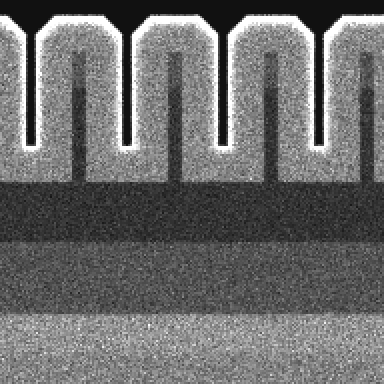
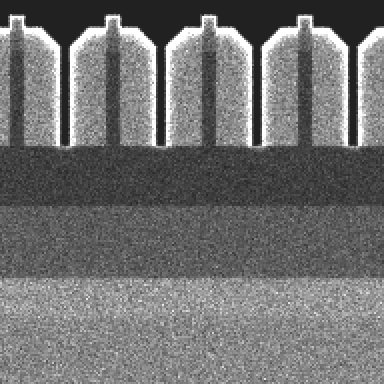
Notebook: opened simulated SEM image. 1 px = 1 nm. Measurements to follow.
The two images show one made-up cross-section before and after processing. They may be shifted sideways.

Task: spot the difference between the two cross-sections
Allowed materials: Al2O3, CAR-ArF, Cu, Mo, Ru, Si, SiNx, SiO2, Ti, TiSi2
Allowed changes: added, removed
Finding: removed SiO2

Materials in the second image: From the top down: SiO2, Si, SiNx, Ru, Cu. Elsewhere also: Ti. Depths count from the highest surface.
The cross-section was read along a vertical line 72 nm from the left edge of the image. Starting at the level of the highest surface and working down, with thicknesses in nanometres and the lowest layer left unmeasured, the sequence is empty 28, SiO2 102, Si 60, SiNx 72, Ru 40, Cu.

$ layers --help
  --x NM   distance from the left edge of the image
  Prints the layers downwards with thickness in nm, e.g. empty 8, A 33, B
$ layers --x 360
empty 28, SiO2 102, Si 60, SiNx 72, Ru 40, Cu